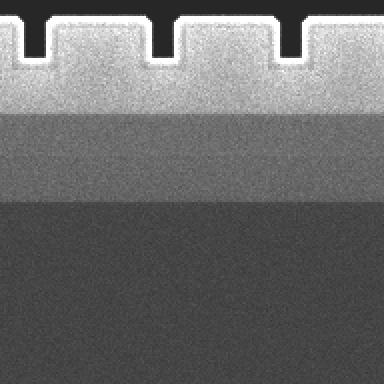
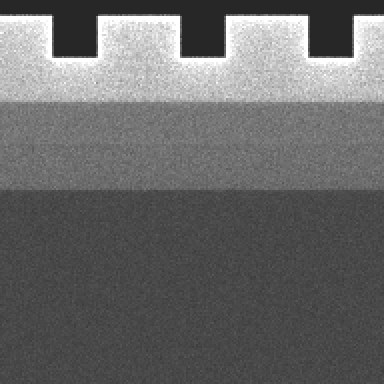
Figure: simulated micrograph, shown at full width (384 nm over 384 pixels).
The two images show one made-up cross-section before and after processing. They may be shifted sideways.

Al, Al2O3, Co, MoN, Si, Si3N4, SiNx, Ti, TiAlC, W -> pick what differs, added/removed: Al2O3 removed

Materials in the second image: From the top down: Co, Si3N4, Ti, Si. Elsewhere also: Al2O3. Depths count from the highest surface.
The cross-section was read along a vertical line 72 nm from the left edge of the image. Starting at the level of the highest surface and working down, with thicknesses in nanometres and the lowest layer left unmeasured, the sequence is empty 42, Co 44, Si3N4 42, Ti 46, Si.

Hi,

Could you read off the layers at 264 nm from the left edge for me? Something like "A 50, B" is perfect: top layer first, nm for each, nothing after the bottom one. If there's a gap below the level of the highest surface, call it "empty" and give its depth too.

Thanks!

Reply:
Co 86, Si3N4 42, Ti 46, Si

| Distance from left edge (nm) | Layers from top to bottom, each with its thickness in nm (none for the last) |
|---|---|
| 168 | Co 86, Si3N4 42, Ti 46, Si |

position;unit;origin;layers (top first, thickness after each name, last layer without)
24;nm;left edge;Co 86, Si3N4 42, Ti 46, Si